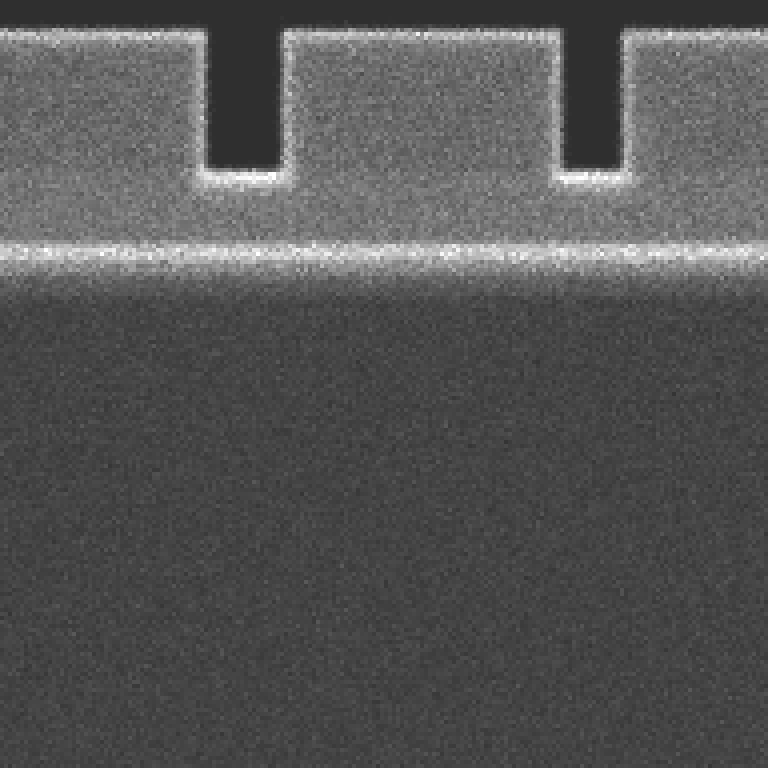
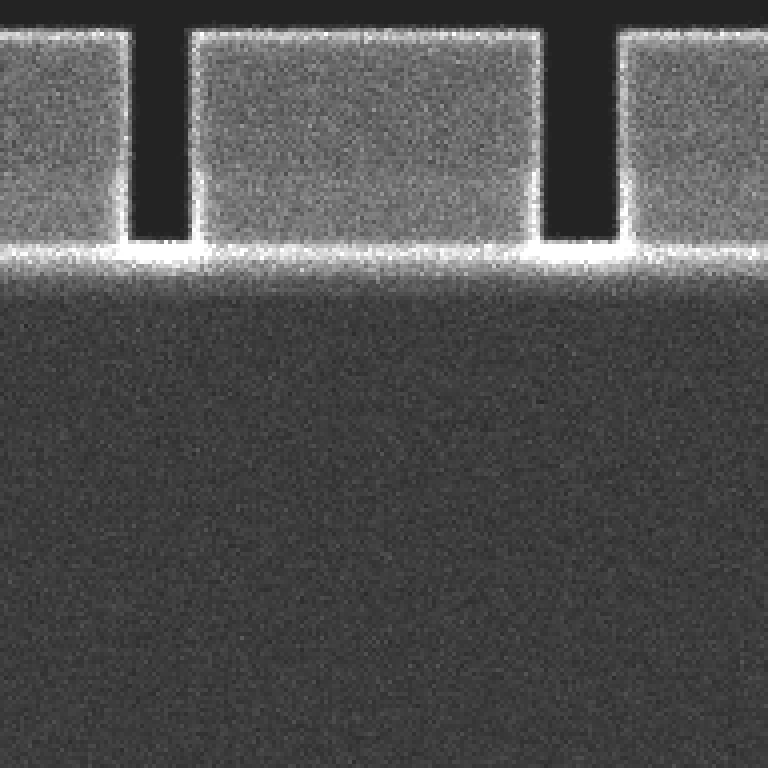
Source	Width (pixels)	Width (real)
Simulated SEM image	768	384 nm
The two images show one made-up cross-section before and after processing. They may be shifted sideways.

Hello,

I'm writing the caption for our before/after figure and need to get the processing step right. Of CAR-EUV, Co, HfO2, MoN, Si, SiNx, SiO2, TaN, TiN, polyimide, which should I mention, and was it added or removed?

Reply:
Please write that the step removed SiO2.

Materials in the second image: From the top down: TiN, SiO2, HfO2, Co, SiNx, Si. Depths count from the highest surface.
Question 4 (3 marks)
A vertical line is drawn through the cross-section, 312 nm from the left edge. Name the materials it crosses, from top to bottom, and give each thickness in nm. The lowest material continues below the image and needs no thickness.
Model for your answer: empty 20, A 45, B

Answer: TiN 70, SiO2 36, HfO2 8, Co 8, SiNx 10, Si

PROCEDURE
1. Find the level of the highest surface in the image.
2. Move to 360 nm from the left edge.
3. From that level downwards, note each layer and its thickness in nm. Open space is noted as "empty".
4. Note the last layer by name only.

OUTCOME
TiN 70, SiO2 36, HfO2 8, Co 8, SiNx 10, Si